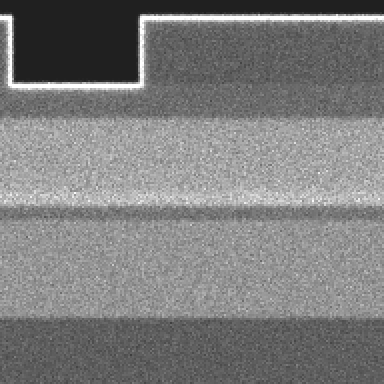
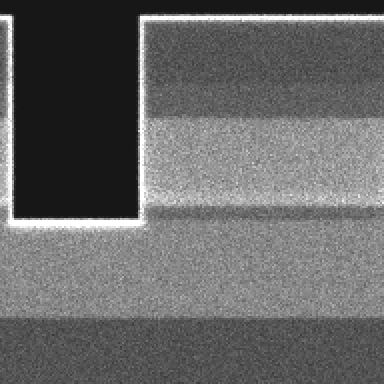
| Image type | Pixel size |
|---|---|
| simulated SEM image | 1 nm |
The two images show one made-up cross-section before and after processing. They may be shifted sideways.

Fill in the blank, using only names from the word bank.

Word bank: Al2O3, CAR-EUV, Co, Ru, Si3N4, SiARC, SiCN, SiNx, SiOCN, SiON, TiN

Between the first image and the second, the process removed Co and Ru and Si3N4 and TiN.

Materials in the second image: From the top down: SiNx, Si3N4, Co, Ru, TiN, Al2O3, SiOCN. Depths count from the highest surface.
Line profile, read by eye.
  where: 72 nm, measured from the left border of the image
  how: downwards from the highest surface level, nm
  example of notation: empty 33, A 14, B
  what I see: empty 204, Al2O3 98, SiOCN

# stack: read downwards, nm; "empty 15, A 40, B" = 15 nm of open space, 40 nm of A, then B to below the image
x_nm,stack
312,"SiNx 68, Si3N4 34, Co 74, Ru 14, TiN 14, Al2O3 98, SiOCN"